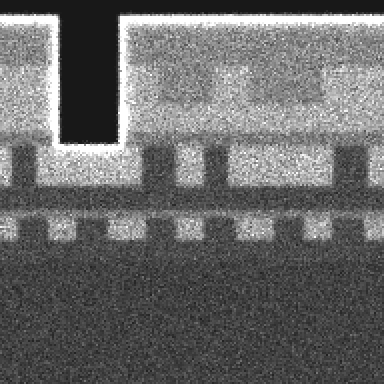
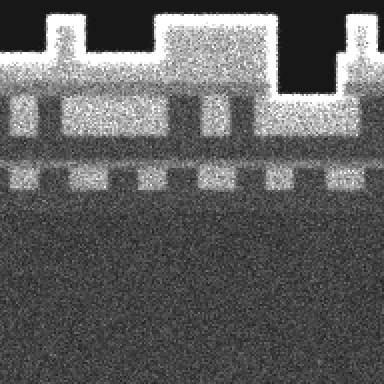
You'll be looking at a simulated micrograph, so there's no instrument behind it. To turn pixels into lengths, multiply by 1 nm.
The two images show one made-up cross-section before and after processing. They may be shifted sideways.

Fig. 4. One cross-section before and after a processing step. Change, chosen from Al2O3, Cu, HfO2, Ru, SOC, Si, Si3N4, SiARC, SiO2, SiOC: SOC removed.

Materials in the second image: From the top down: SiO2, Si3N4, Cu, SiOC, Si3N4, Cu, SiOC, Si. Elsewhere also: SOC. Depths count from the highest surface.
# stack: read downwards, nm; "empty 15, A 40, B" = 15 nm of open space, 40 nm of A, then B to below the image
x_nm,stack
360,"SiO2 66, Si3N4 14, SiOC 64, Si3N4 8, Cu 22, SiOC 22, Si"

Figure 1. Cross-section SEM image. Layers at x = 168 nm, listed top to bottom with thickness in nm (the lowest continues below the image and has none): SiO2 66, Si3N4 14, SiOC 64, Si3N4 8, SiOC 44, Si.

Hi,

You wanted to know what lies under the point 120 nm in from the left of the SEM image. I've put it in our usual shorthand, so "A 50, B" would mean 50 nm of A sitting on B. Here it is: empty 38, SiO2 28, Si3N4 14, Cu 40, SiOC 24, Si3N4 8, SiOC 44, Si